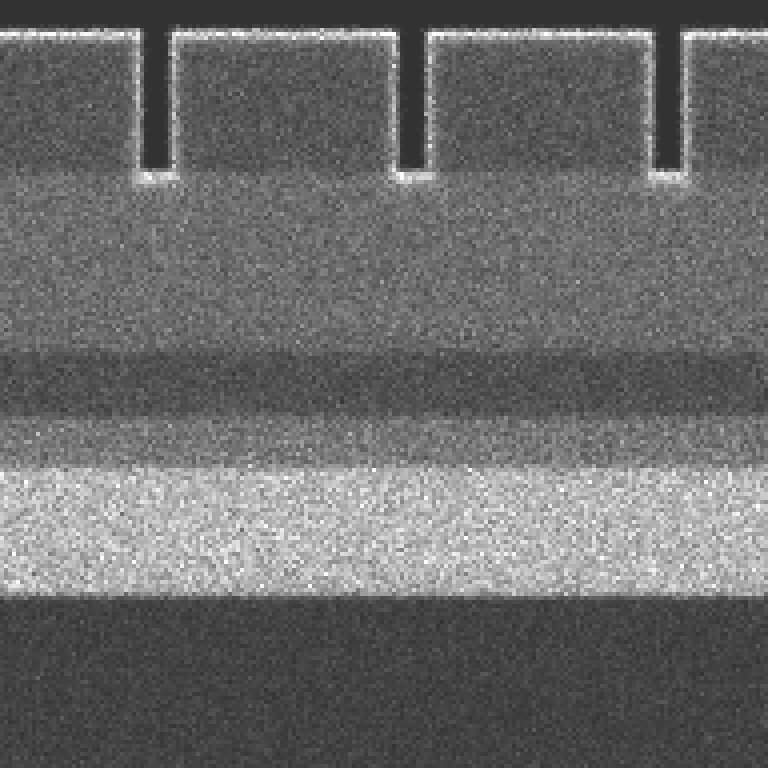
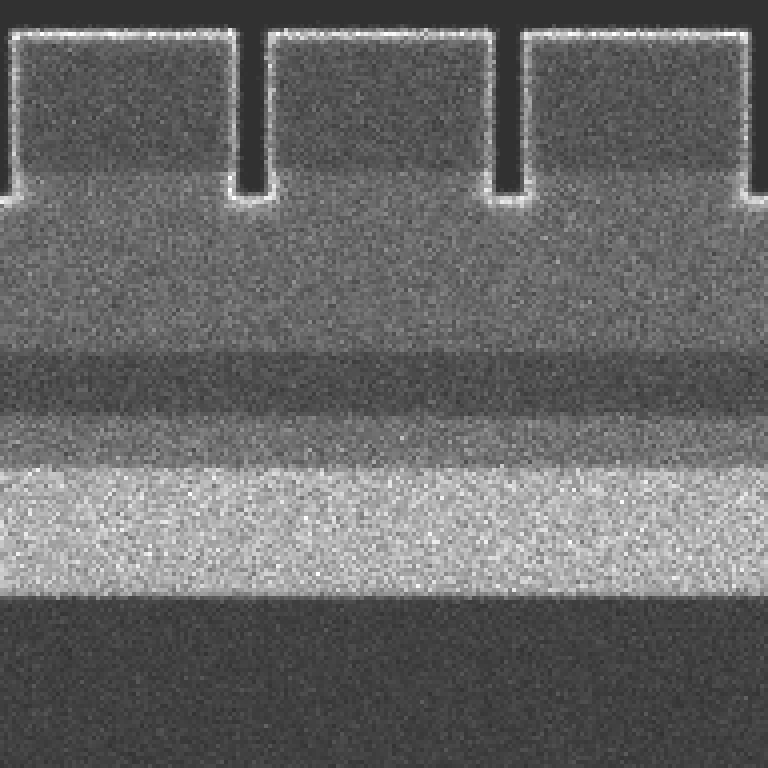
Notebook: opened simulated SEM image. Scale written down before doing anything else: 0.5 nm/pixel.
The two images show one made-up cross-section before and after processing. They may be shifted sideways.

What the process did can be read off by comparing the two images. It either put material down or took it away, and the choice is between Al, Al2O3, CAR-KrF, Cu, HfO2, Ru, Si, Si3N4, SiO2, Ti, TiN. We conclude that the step removed SiO2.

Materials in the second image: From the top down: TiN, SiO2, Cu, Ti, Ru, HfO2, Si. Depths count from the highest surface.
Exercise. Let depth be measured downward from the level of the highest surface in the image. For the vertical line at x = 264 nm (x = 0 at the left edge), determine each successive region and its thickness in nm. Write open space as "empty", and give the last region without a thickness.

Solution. TiN 70, SiO2 76, Cu 14, Ti 32, Ru 26, HfO2 64, Si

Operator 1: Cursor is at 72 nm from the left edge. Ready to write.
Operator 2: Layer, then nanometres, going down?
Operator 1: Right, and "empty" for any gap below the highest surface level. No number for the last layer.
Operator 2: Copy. TiN 70, SiO2 76, Cu 14, Ti 32, Ru 26, HfO2 64, Si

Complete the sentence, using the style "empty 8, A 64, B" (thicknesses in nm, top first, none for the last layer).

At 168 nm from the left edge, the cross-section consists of TiN 70, SiO2 76, Cu 14, Ti 32, Ru 26, HfO2 64, Si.